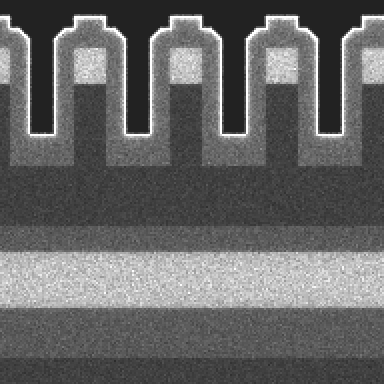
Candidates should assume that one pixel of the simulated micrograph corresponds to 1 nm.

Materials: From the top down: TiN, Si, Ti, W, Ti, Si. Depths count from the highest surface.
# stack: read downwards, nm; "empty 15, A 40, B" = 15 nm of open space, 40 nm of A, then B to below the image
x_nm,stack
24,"empty 18, TiN 132, Si 60, Ti 26, W 56, Ti 50, Si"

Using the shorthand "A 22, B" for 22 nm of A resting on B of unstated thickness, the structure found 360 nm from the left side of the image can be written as empty 12, TiN 138, Si 60, Ti 26, W 56, Ti 50, Si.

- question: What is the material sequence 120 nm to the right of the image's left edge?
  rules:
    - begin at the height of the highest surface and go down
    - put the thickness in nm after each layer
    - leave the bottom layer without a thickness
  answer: empty 18, TiN 132, Si 60, Ti 26, W 56, Ti 50, Si